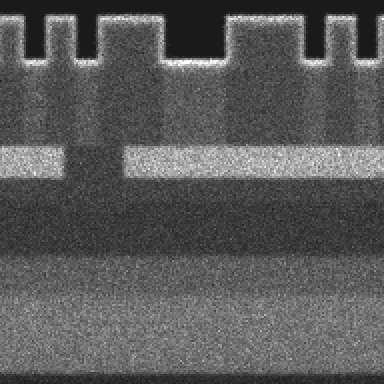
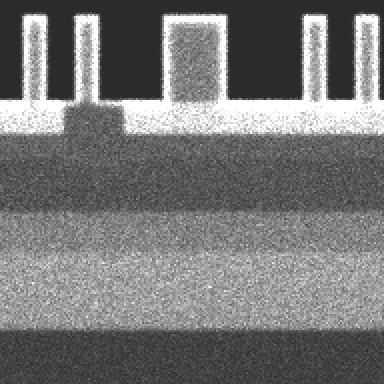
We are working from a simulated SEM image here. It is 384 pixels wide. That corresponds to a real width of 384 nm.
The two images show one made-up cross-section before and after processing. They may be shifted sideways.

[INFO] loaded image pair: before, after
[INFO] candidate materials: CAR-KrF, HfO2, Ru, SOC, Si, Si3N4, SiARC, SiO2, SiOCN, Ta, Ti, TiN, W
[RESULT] removed SOC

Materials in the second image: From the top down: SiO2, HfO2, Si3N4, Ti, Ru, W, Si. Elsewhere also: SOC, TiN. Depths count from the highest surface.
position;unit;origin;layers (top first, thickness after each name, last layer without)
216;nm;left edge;SiO2 86, HfO2 32, Si3N4 24, Ti 54, Ru 40, W 78, Si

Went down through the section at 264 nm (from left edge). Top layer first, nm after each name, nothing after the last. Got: empty 86, HfO2 32, Si3N4 24, Ti 54, Ru 40, W 78, Si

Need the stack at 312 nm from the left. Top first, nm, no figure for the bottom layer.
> SiO2 86, HfO2 32, Si3N4 24, Ti 54, Ru 40, W 78, Si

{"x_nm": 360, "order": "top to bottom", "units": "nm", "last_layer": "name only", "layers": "SiO2 86, HfO2 32, Si3N4 24, Ti 54, Ru 40, W 78, Si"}